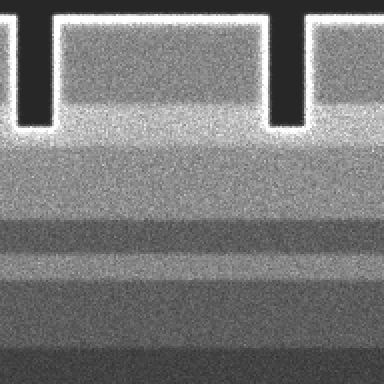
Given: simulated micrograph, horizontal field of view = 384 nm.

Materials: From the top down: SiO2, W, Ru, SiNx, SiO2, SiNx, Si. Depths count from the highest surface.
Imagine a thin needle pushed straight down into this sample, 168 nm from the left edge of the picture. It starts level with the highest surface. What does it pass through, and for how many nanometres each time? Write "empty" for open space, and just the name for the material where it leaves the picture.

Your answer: SiO2 88, W 42, Ru 74, SiNx 34, SiO2 26, SiNx 68, Si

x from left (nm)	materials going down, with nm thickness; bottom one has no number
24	empty 112, W 18, Ru 74, SiNx 34, SiO2 26, SiNx 68, Si